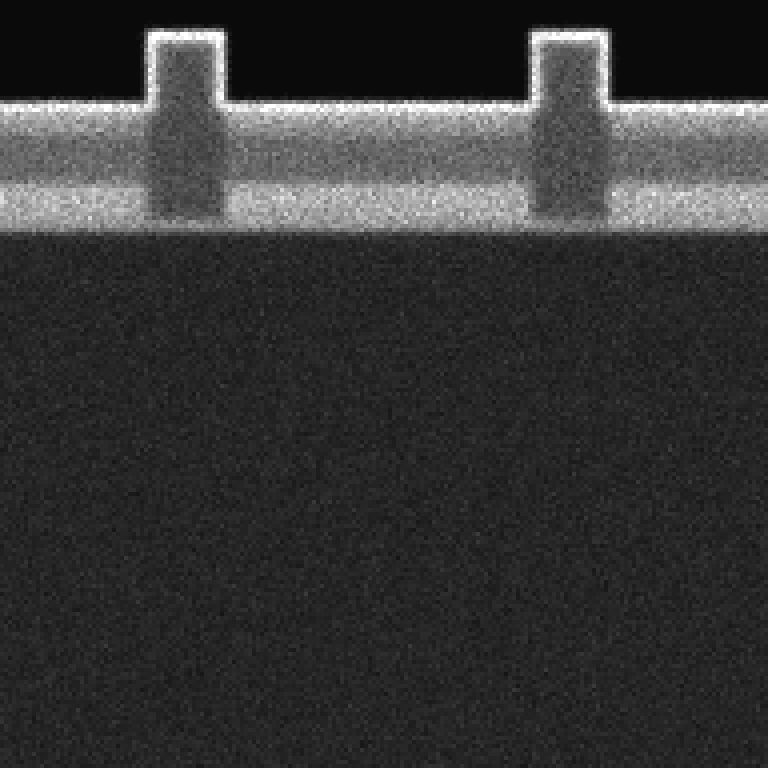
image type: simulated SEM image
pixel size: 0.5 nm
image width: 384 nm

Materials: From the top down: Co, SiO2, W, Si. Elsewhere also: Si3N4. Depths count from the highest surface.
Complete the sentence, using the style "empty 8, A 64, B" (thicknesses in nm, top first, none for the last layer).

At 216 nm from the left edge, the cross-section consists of empty 36, Co 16, SiO2 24, W 24, Si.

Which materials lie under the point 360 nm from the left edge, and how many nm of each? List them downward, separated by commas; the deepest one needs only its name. empty 36, Co 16, SiO2 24, W 24, Si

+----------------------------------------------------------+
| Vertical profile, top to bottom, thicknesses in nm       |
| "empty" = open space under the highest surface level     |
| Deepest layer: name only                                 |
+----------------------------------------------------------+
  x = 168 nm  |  empty 36, Co 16, SiO2 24, W 24, Si